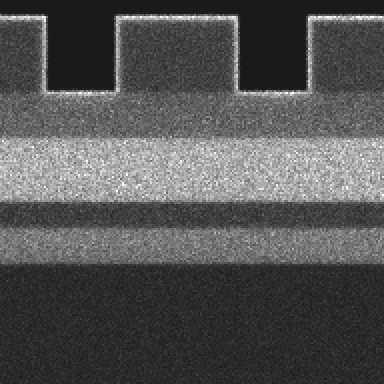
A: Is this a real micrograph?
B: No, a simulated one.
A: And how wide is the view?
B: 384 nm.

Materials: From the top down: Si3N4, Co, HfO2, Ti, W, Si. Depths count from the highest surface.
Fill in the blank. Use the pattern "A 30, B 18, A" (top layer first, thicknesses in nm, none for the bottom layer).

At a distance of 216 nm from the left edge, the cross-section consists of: Si3N4 76, Co 46, HfO2 64, Ti 26, W 36, Si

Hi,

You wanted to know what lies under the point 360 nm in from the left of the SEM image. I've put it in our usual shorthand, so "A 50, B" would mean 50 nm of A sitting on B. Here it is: Si3N4 76, Co 46, HfO2 64, Ti 26, W 36, Si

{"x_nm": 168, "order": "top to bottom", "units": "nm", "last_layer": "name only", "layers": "Si3N4 76, Co 46, HfO2 64, Ti 26, W 36, Si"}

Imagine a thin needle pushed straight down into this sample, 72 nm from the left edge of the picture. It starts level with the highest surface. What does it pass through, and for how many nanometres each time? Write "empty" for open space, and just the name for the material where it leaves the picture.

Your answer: empty 76, Co 46, HfO2 64, Ti 26, W 36, Si